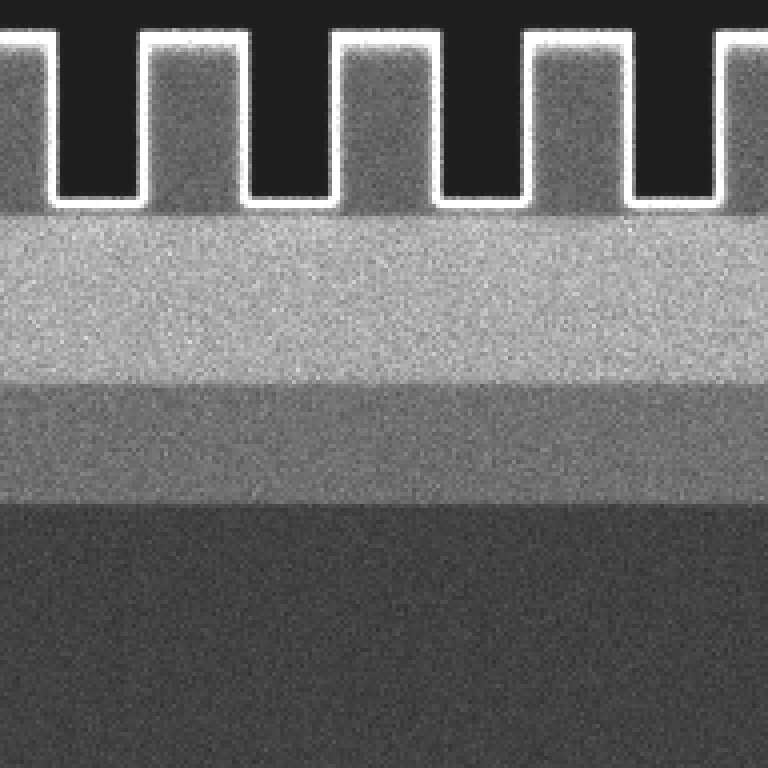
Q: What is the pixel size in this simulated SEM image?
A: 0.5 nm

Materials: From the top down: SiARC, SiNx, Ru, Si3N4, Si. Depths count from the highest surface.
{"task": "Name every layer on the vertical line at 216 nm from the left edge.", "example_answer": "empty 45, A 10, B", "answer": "SiARC 12, SiNx 80, Ru 84, Si3N4 60, Si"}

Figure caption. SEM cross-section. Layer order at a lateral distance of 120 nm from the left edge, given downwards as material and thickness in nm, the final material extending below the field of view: SiARC 12, SiNx 80, Ru 84, Si3N4 60, Si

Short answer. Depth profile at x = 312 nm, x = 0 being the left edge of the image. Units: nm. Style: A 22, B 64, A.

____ SiARC 12, SiNx 80, Ru 84, Si3N4 60, Si